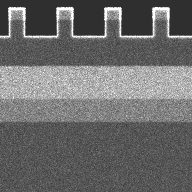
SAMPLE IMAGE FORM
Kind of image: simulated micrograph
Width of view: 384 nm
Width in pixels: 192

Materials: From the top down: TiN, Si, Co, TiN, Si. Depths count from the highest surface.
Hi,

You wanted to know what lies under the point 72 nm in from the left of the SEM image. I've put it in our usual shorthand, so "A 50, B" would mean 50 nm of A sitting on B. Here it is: empty 56, Si 60, Co 66, TiN 46, Si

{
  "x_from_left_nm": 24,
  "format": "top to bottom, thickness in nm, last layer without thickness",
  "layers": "TiN 24, Si 92, Co 66, TiN 46, Si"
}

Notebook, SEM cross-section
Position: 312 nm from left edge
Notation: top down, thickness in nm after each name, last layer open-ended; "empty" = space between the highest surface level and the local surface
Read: TiN 24, Si 92, Co 66, TiN 46, Si